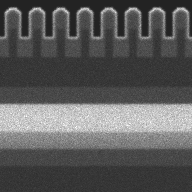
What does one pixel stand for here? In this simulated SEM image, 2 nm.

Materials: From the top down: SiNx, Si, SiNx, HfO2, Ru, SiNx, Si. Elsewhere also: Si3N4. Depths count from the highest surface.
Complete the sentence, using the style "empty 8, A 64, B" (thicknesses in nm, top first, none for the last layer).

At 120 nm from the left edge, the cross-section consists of SiNx 42, Si 116, SiNx 34, HfO2 56, Ru 34, SiNx 34, Si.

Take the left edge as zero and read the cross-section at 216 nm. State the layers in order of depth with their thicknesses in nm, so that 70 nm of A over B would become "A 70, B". SiNx 42, Si 116, SiNx 34, HfO2 56, Ru 34, SiNx 34, Si